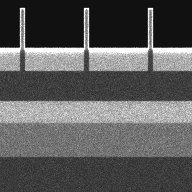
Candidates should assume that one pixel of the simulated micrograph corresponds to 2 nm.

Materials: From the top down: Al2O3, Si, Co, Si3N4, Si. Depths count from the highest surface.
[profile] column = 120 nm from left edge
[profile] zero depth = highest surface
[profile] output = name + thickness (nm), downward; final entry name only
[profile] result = empty 80, Al2O3 46, Si 60, Co 44, Si3N4 68, Si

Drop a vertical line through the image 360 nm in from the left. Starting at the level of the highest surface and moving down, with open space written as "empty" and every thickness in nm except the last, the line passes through empty 80, Al2O3 46, Si 60, Co 44, Si3N4 68, Si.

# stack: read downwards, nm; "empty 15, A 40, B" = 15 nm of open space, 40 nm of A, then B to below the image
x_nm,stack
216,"empty 80, Al2O3 46, Si 60, Co 44, Si3N4 68, Si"